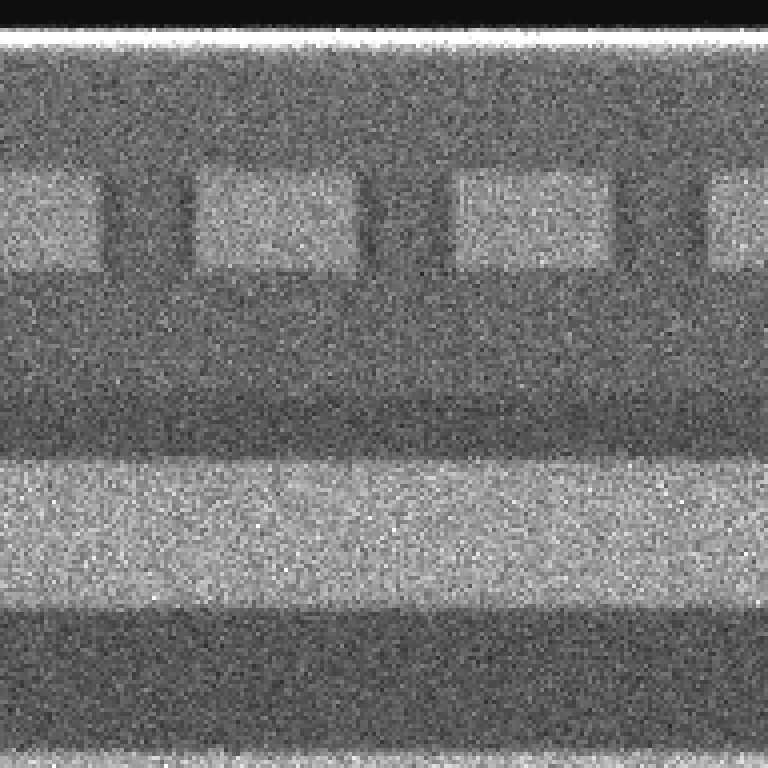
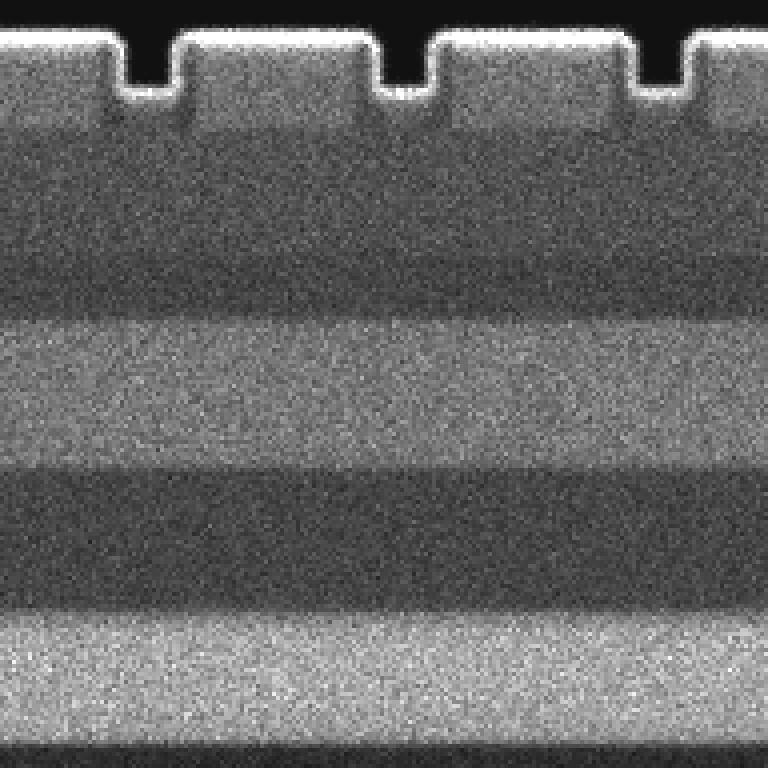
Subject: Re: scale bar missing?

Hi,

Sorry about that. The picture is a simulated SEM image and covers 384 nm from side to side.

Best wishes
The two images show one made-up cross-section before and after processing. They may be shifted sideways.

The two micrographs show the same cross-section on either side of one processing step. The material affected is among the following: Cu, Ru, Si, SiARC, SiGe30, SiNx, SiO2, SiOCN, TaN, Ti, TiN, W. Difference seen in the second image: SiARC removed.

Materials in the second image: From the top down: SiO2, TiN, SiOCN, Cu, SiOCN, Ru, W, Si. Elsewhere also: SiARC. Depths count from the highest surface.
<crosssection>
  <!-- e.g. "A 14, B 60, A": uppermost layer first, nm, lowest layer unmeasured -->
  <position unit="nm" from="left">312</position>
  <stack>empty 2, SiOCN 46, TiN 64, SiOCN 32, Cu 74, SiOCN 72, Ru 8, W 58, Si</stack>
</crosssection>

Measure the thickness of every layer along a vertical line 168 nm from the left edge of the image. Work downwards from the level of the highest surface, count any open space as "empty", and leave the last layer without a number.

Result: SiO2 48, TiN 64, SiOCN 32, Cu 74, SiOCN 72, Ru 8, W 58, Si